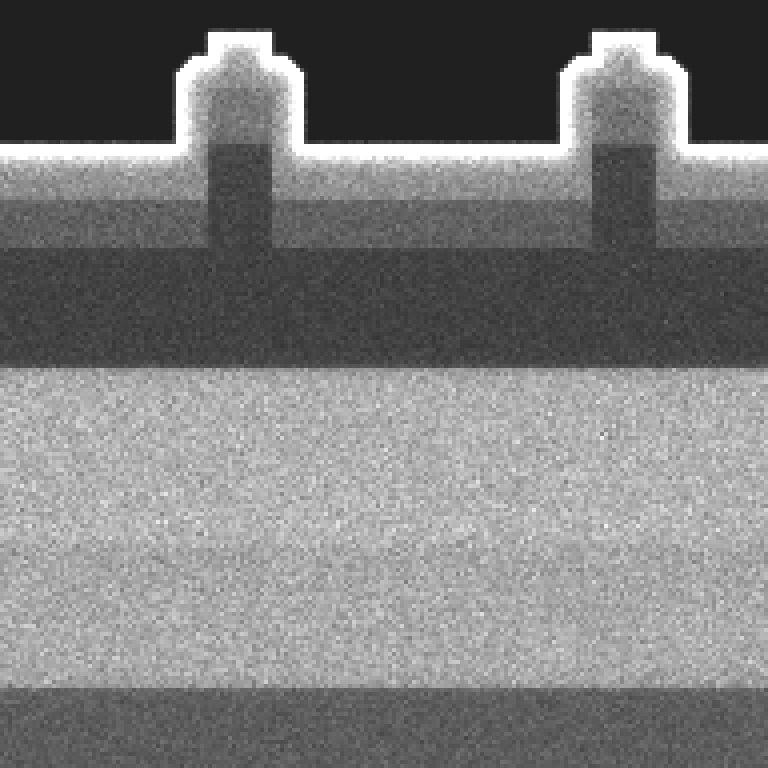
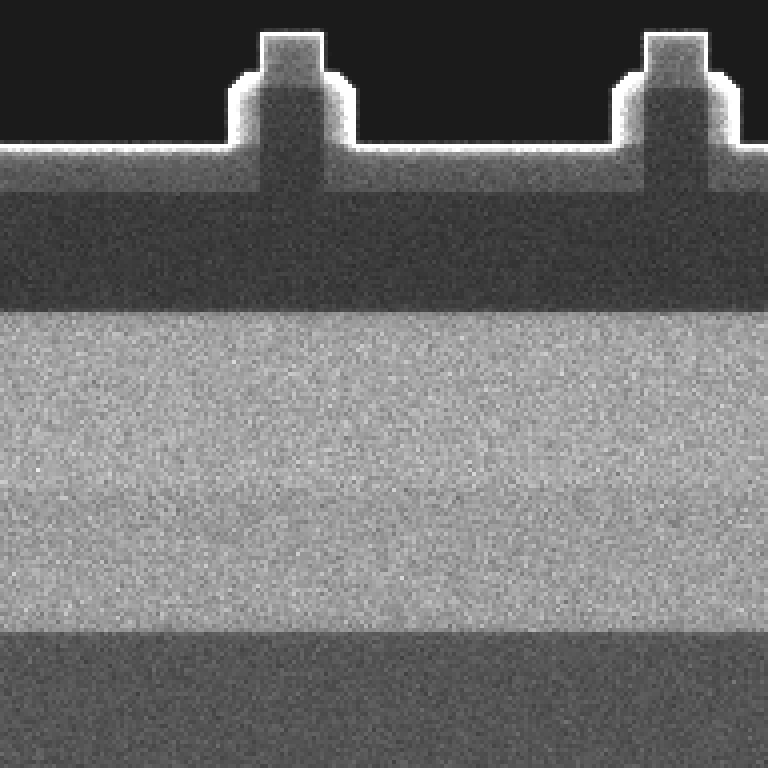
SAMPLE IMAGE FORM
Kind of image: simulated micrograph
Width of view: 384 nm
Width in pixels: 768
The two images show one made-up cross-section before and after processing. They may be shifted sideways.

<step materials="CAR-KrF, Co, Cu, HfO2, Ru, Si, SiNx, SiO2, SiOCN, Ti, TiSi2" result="removed SiO2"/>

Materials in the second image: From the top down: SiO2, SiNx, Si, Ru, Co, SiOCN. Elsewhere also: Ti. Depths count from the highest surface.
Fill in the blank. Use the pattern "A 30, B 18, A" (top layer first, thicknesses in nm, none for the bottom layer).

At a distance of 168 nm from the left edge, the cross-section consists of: empty 20, SiO2 36, SiNx 24, Si 60, Ru 88, Co 72, SiOCN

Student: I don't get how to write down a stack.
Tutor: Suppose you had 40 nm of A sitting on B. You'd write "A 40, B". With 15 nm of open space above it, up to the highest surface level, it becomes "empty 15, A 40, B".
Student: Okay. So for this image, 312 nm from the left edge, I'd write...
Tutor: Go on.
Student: empty 22, SiO2 34, SiNx 24, Si 60, Ru 88, Co 72, SiOCN